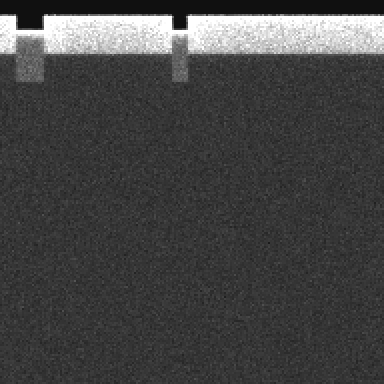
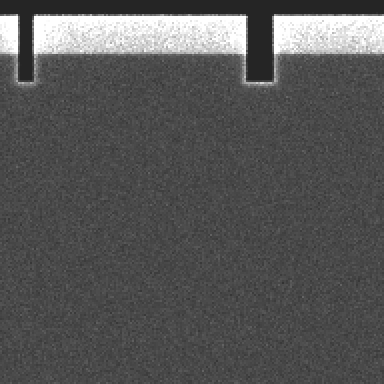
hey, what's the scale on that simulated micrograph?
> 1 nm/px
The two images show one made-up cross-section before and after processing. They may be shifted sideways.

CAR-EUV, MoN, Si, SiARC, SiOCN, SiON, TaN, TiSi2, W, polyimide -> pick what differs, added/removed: SiARC removed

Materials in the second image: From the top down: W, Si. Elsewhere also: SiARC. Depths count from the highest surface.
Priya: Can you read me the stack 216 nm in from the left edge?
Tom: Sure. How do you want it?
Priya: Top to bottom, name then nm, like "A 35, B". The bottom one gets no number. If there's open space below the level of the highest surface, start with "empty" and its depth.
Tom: W 38, Si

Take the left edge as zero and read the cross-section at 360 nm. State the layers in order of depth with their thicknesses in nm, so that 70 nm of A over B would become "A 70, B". W 38, Si